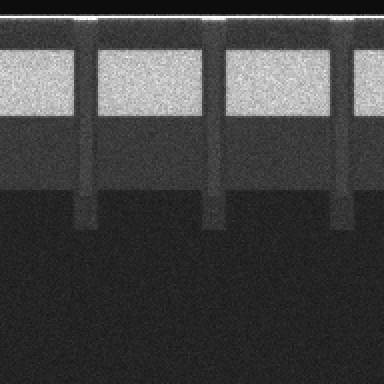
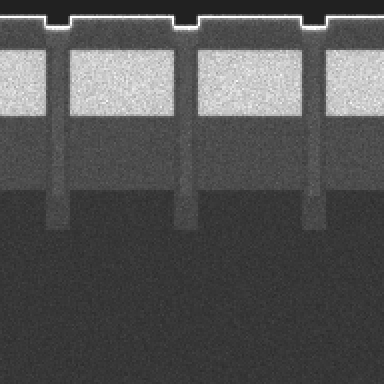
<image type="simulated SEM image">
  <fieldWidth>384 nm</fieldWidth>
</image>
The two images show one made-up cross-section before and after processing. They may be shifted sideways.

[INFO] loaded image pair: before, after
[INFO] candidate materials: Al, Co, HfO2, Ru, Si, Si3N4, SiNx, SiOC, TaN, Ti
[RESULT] removed Si3N4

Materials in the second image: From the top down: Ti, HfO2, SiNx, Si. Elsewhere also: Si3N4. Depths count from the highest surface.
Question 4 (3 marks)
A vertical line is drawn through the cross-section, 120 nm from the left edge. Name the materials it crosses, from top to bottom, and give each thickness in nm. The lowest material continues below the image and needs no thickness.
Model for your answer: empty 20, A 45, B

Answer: Ti 34, HfO2 66, SiNx 74, Si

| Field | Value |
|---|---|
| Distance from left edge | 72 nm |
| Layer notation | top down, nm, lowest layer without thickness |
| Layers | Ti 34, HfO2 66, SiNx 74, Si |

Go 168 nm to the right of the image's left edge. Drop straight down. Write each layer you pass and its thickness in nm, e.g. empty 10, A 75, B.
Ti 34, HfO2 66, SiNx 74, Si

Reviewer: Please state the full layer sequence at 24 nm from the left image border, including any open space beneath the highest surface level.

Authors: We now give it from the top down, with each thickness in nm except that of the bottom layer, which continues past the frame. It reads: Ti 34, HfO2 66, SiNx 74, Si